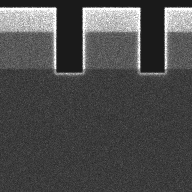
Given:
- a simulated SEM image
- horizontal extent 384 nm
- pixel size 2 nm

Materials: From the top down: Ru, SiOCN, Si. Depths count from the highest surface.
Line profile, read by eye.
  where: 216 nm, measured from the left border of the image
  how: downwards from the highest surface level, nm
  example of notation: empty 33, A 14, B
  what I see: Ru 48, SiOCN 74, Si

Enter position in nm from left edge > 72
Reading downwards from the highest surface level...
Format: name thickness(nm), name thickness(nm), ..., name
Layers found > Ru 48, SiOCN 74, Si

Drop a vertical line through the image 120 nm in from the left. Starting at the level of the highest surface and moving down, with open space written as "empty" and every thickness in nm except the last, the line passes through empty 130, Si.